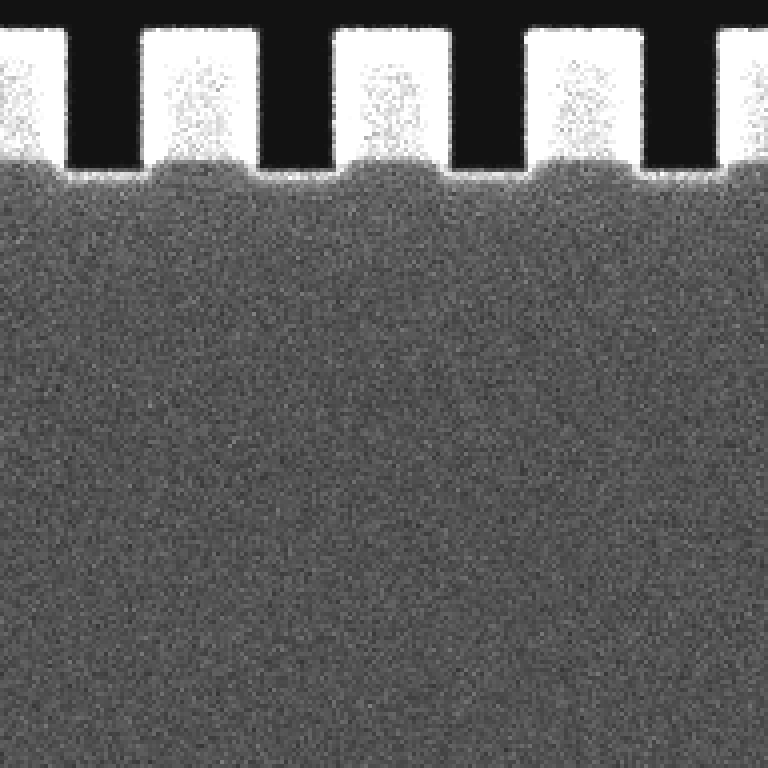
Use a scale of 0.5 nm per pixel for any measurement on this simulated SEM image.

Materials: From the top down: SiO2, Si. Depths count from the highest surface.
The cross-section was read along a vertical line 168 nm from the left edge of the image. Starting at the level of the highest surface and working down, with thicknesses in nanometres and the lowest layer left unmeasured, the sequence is SiO2 64, Si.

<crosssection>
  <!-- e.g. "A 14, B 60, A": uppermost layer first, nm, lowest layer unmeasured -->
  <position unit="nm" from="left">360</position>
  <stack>SiO2 64, Si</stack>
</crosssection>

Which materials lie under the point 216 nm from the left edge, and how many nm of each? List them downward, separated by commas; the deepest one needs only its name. SiO2 64, Si